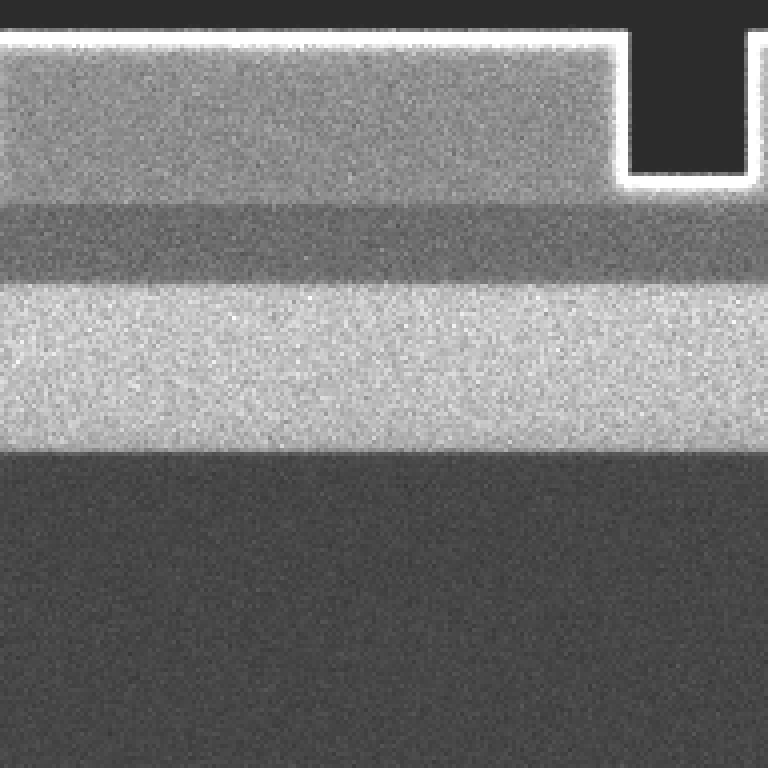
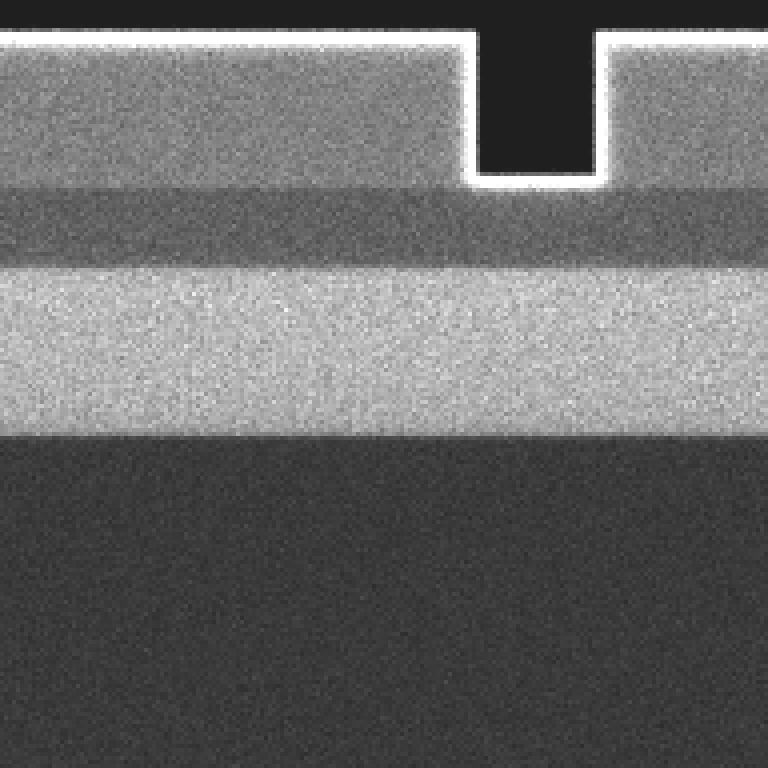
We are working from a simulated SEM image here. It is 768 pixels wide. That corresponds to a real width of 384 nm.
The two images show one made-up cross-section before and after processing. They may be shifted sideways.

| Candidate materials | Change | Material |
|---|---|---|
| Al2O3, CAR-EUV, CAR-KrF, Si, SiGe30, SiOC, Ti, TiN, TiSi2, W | removed | Al2O3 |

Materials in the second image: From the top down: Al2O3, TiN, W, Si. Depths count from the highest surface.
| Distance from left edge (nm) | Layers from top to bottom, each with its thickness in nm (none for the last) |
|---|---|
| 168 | Al2O3 78, TiN 40, W 84, Si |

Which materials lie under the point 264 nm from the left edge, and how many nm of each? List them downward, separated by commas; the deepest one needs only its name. empty 72, Al2O3 6, TiN 40, W 84, Si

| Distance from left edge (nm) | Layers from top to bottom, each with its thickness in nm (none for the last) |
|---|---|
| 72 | Al2O3 78, TiN 40, W 84, Si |